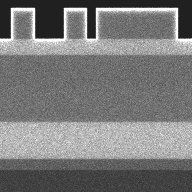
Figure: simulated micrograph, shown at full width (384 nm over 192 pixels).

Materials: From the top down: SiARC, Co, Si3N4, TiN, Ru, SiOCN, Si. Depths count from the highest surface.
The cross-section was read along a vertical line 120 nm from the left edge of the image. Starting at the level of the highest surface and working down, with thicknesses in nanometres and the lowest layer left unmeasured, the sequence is empty 62, Co 32, Si3N4 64, TiN 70, Ru 74, SiOCN 22, Si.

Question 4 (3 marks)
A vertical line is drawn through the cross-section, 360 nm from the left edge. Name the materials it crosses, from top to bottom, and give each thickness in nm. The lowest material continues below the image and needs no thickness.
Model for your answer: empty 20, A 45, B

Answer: empty 62, Co 32, Si3N4 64, TiN 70, Ru 74, SiOCN 22, Si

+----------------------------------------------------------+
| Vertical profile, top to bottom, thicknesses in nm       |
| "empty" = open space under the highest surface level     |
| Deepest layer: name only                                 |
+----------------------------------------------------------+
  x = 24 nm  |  SiARC 62, Co 32, Si3N4 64, TiN 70, Ru 74, SiOCN 22, Si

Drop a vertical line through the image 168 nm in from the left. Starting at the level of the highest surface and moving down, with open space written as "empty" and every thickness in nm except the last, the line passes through SiARC 62, Co 32, Si3N4 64, TiN 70, Ru 74, SiOCN 22, Si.